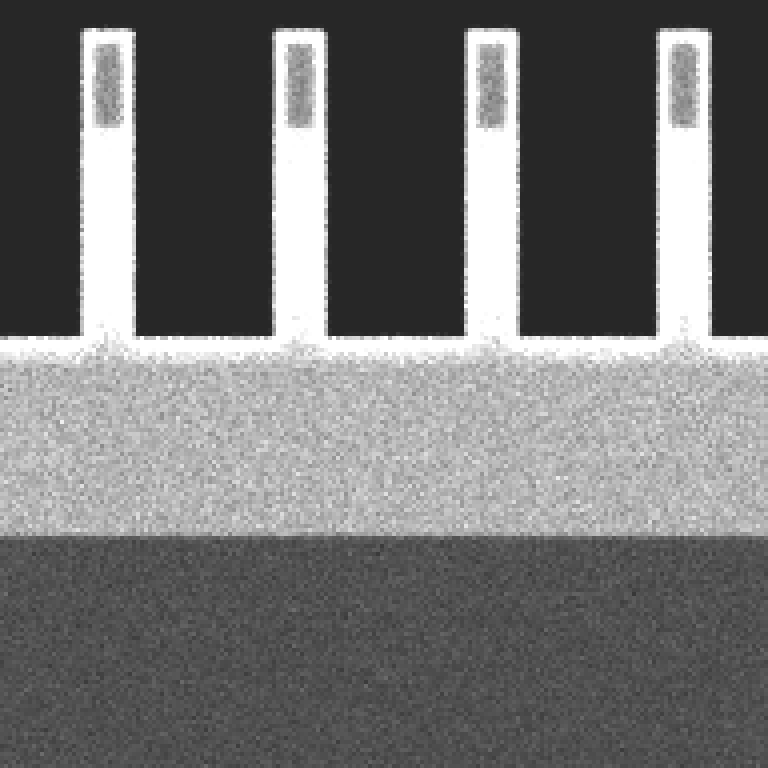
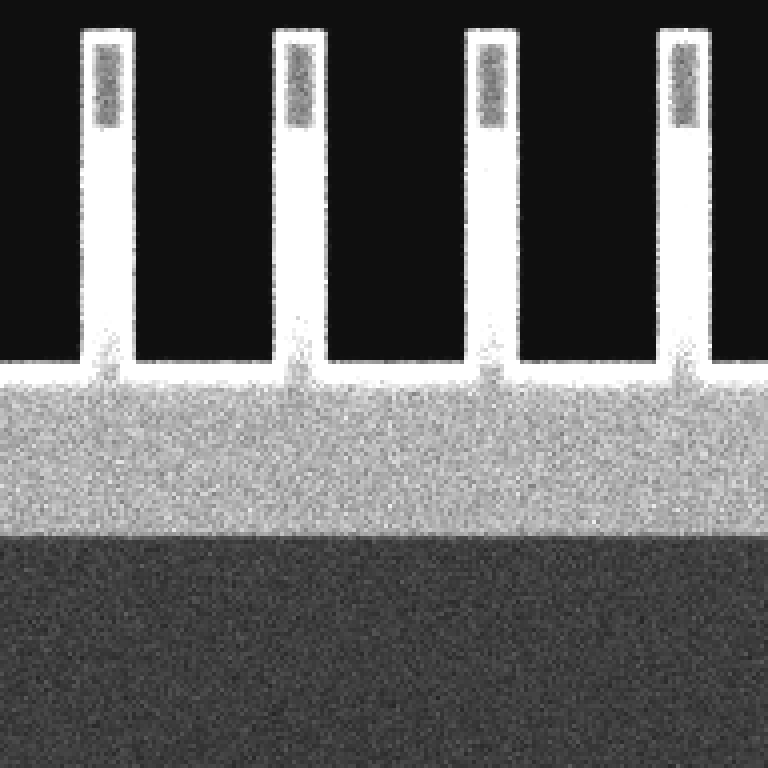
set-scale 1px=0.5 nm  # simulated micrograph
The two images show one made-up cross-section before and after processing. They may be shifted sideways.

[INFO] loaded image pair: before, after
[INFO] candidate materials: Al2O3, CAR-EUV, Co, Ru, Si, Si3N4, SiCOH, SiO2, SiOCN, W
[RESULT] removed Co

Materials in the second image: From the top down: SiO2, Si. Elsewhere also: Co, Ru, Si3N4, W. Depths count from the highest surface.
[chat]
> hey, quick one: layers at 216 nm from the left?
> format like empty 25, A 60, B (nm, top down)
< empty 166, SiO2 86, Si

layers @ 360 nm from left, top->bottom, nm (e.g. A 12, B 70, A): empty 166, SiO2 86, Si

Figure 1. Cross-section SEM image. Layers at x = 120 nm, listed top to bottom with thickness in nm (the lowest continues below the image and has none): empty 166, SiO2 86, Si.